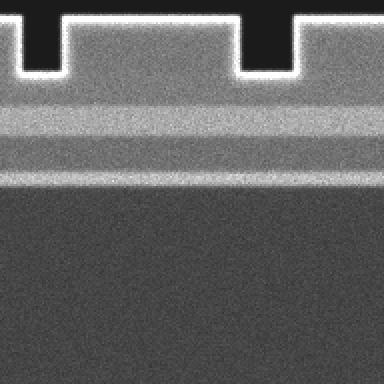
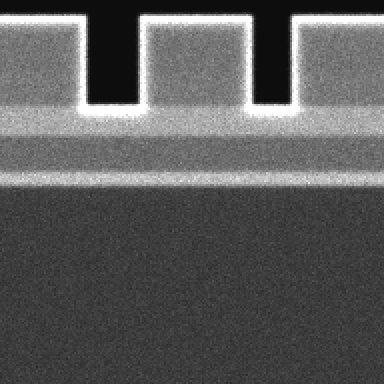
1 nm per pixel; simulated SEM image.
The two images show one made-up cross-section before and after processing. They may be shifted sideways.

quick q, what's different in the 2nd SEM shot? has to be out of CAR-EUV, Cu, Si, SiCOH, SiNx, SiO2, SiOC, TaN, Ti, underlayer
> underlayer removed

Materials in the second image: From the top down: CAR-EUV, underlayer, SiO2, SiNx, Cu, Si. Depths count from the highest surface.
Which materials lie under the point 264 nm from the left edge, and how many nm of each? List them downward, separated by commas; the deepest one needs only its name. empty 90, SiO2 30, SiNx 36, Cu 14, Si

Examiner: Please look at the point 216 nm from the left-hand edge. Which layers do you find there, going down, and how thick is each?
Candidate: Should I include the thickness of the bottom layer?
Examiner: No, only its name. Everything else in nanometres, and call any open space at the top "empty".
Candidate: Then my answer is CAR-EUV 56, underlayer 34, SiO2 30, SiNx 36, Cu 14, Si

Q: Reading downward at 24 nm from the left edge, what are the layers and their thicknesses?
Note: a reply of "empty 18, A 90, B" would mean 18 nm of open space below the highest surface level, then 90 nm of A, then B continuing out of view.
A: CAR-EUV 56, underlayer 34, SiO2 30, SiNx 36, Cu 14, Si